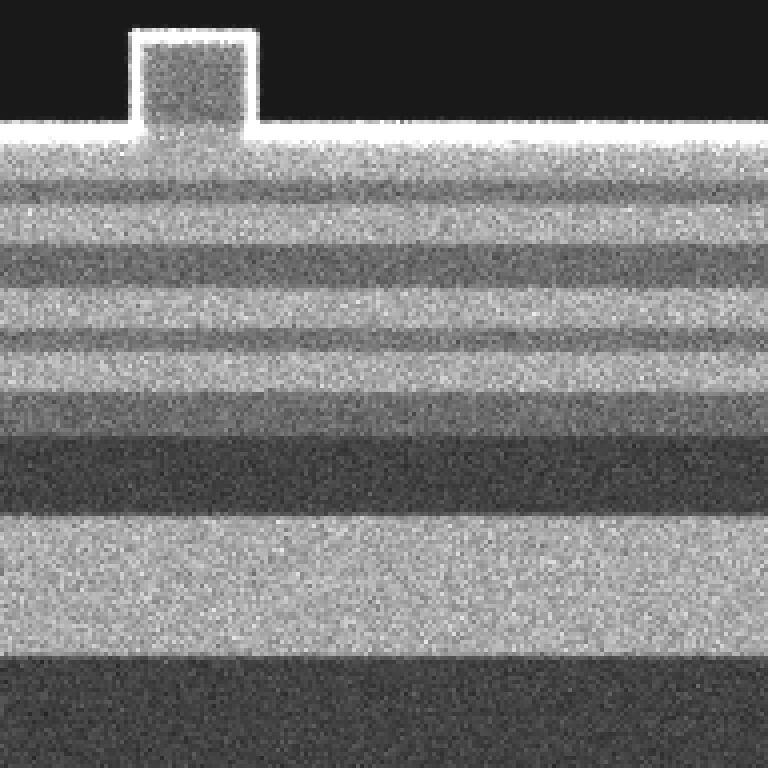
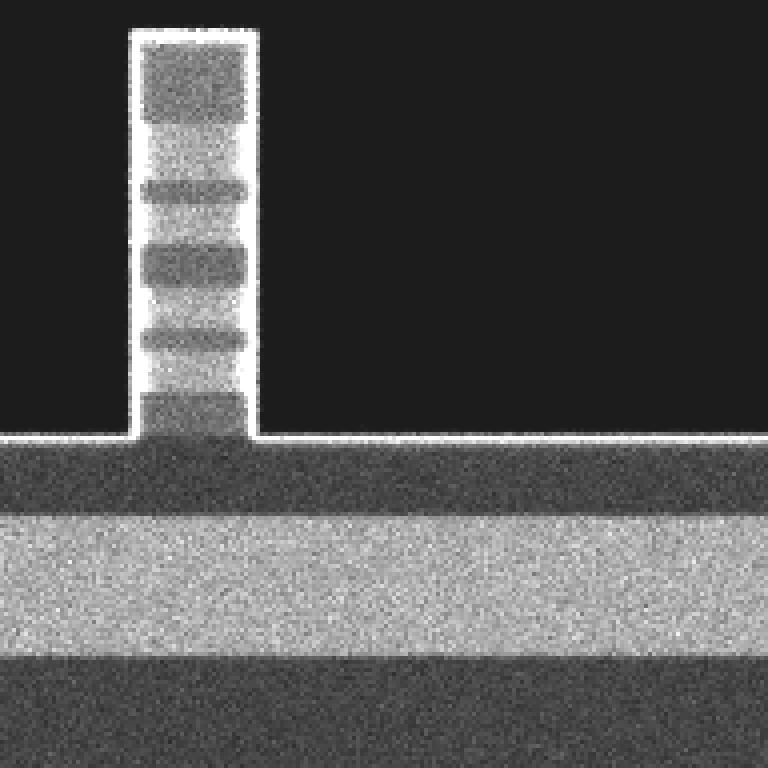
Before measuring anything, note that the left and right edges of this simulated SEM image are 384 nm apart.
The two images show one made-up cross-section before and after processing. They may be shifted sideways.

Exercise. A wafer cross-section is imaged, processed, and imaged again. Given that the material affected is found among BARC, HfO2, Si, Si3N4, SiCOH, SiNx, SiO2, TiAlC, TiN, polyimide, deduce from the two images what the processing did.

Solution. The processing removed SiNx and SiO2 and TiN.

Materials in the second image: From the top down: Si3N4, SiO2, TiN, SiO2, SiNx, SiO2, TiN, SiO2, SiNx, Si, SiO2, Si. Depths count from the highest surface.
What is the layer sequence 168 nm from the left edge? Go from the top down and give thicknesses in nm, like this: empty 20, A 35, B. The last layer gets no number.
empty 202, Si 40, SiO2 70, Si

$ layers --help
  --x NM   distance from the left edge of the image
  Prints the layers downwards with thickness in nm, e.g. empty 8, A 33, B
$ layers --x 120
Si3N4 46, SiO2 28, TiN 12, SiO2 20, SiNx 22, SiO2 20, TiN 12, SiO2 20, SiNx 22, Si 40, SiO2 70, Si